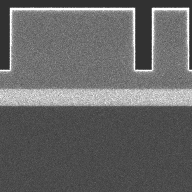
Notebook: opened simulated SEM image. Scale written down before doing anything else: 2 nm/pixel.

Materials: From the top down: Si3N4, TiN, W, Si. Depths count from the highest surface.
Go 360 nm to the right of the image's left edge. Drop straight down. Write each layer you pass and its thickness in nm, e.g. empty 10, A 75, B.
Si3N4 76, TiN 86, W 34, Si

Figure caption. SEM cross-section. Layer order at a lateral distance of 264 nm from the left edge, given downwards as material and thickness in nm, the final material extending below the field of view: Si3N4 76, TiN 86, W 34, Si